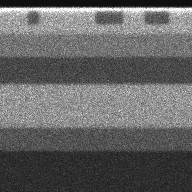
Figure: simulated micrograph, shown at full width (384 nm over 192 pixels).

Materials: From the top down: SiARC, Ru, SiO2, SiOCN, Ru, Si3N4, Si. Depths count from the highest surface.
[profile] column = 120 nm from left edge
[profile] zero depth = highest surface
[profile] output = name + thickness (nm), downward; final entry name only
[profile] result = SiARC 6, Ru 46, SiO2 46, SiOCN 54, Ru 88, Si3N4 46, Si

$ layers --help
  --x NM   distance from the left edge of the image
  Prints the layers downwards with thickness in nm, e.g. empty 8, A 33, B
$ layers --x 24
SiARC 6, Ru 46, SiO2 46, SiOCN 54, Ru 88, Si3N4 46, Si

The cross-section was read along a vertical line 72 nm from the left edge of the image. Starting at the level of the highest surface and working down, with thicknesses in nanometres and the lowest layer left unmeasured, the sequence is SiARC 32, Ru 20, SiO2 46, SiOCN 54, Ru 88, Si3N4 46, Si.